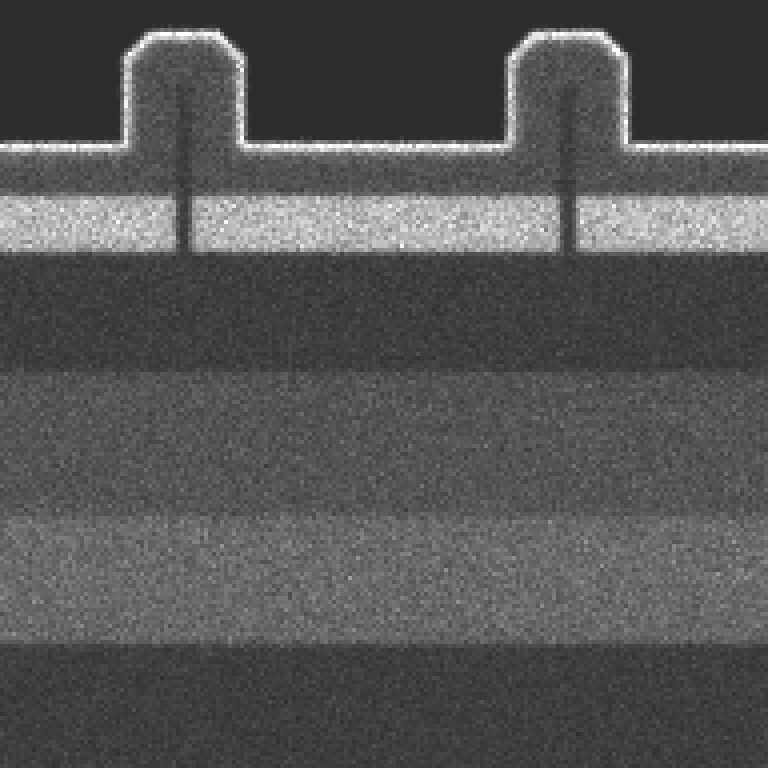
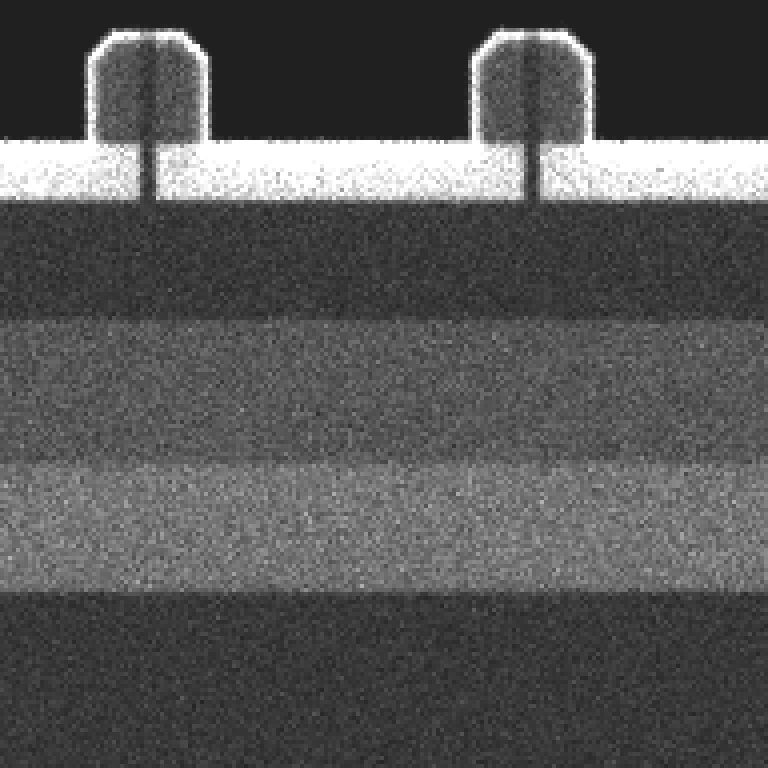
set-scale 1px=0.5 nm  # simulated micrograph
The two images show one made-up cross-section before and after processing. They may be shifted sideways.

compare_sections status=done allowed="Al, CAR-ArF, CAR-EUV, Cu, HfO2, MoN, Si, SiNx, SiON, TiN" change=removed material="SiNx"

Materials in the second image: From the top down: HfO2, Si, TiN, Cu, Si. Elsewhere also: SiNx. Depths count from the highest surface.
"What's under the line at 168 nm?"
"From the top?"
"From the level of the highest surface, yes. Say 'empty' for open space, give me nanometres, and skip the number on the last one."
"empty 56, HfO2 28, Si 60, TiN 72, Cu 64, Si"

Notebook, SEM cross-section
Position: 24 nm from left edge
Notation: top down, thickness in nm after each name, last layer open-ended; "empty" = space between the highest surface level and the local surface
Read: empty 56, HfO2 28, Si 60, TiN 72, Cu 64, Si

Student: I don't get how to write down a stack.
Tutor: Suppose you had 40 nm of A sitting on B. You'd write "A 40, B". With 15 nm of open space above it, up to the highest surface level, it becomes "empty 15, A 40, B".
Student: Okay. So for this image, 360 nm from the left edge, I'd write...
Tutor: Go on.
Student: empty 56, HfO2 28, Si 60, TiN 72, Cu 64, Si